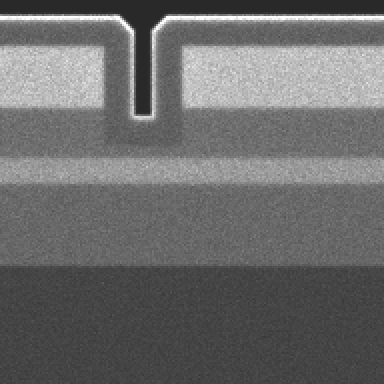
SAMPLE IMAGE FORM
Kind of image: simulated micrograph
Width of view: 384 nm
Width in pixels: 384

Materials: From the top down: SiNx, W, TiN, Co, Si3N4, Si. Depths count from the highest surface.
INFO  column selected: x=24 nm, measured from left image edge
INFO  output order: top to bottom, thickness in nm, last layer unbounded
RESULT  SiNx 30, W 62, TiN 50, Co 26, Si3N4 82, Si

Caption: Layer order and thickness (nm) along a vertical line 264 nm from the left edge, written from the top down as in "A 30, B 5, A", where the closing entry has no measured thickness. SiNx 30, W 62, TiN 50, Co 26, Si3N4 82, Si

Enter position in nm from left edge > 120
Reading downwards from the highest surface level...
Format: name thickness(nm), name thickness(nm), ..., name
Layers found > empty 2, SiNx 128, TiN 12, Co 26, Si3N4 82, Si